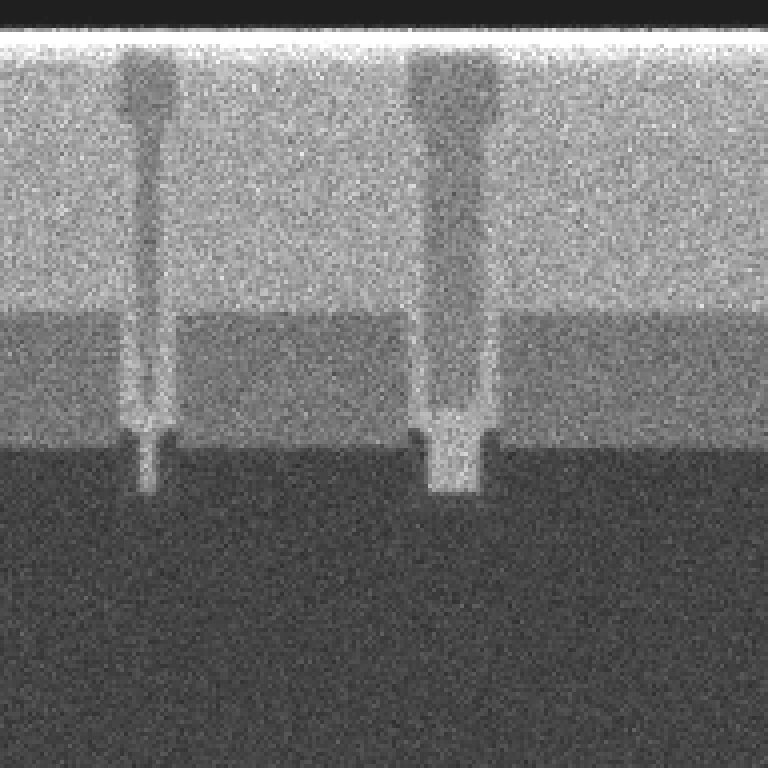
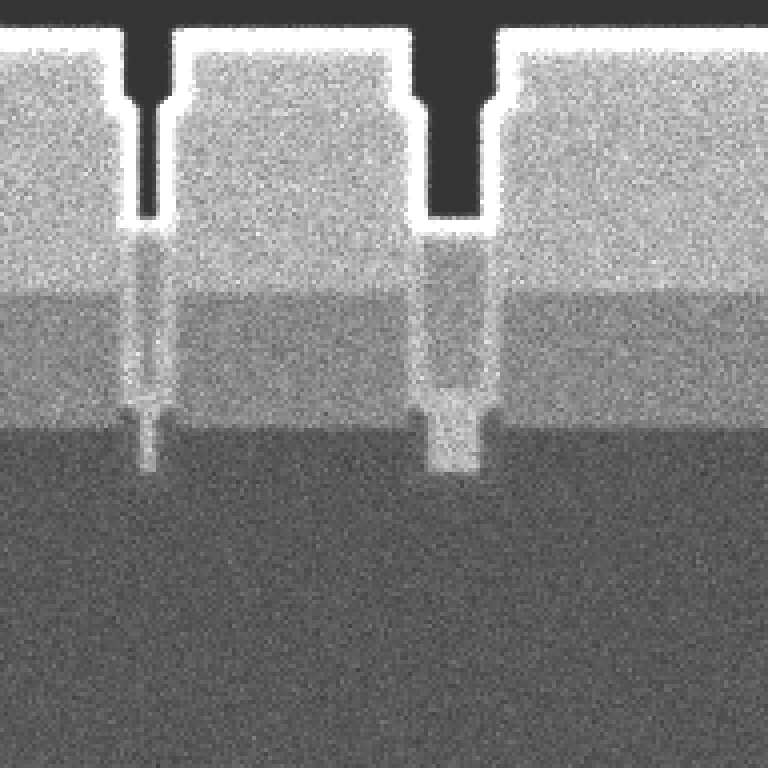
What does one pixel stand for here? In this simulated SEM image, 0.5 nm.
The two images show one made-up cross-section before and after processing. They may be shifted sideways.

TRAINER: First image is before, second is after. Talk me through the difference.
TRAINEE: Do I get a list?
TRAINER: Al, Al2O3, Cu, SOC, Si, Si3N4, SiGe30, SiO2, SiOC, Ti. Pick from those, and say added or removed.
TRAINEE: removed: SOC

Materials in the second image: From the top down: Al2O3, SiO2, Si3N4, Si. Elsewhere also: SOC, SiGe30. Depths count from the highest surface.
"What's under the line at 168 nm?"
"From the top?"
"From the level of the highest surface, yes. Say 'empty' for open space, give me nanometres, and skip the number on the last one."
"Al2O3 42, SiO2 88, Si3N4 68, Si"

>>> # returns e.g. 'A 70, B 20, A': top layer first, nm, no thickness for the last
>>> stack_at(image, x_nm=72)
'empty 94, SOC 84, Al2O3 42, SiGe30 10, Si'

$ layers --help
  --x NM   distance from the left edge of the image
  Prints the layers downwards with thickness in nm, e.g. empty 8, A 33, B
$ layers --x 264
Al2O3 42, SiO2 88, Si3N4 68, Si